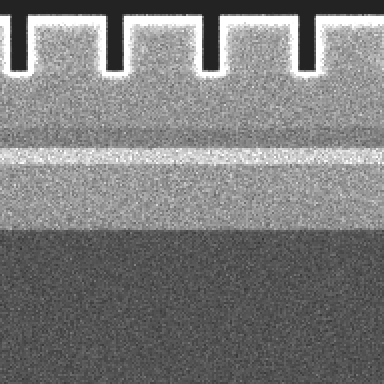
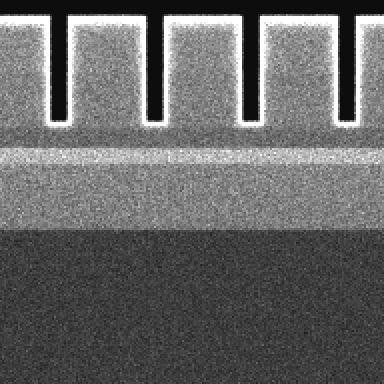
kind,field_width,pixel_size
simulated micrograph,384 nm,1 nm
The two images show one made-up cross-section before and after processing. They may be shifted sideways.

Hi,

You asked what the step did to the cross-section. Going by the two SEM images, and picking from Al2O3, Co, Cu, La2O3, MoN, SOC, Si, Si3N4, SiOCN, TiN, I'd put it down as Si3N4, removed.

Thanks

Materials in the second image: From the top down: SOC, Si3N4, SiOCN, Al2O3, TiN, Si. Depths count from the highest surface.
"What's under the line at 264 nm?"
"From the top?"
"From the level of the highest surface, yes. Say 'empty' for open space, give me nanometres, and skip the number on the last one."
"SOC 56, Si3N4 56, SiOCN 20, Al2O3 16, TiN 66, Si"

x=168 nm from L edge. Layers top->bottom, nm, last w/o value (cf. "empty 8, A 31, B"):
SOC 56, Si3N4 56, SiOCN 20, Al2O3 16, TiN 66, Si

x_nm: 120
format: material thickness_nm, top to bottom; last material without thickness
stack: SOC 56, Si3N4 56, SiOCN 20, Al2O3 16, TiN 66, Si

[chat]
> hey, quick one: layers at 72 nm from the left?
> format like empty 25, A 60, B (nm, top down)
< SOC 56, Si3N4 56, SiOCN 20, Al2O3 16, TiN 66, Si